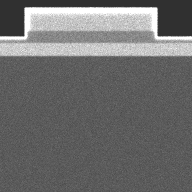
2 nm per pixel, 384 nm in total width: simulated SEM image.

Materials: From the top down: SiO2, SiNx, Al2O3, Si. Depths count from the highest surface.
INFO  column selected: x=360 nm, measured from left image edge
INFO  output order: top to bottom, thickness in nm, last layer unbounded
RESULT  empty 58, SiNx 12, Al2O3 26, Si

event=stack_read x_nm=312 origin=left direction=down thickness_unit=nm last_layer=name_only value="SiO2 46, SiNx 24, Al2O3 26, Si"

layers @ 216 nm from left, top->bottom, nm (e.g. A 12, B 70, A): SiO2 46, SiNx 24, Al2O3 26, Si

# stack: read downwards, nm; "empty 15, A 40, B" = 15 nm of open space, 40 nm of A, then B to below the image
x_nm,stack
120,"SiO2 46, SiNx 24, Al2O3 26, Si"